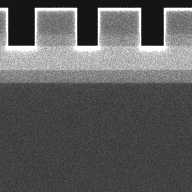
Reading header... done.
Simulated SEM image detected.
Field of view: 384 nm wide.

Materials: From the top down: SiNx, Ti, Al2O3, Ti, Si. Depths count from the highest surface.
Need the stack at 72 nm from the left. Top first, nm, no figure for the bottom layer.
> SiNx 52, Ti 24, Al2O3 48, Ti 26, Si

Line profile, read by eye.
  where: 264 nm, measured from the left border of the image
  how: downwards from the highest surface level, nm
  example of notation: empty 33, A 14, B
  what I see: SiNx 52, Ti 24, Al2O3 48, Ti 26, Si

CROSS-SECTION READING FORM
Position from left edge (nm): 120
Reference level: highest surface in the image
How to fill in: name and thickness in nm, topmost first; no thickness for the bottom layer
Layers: SiNx 52, Ti 24, Al2O3 48, Ti 26, Si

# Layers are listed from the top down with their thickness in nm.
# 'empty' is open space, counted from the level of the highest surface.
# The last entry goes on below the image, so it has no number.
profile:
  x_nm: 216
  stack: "SiNx 52, Ti 24, Al2O3 48, Ti 26, Si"